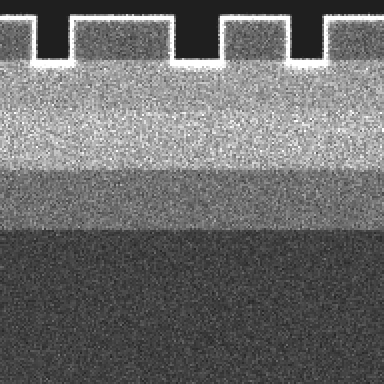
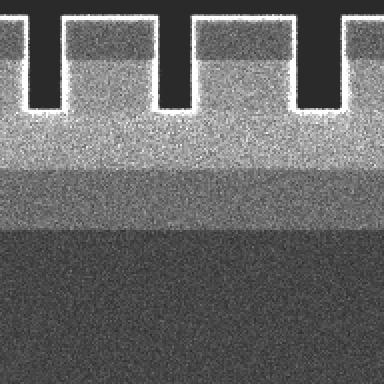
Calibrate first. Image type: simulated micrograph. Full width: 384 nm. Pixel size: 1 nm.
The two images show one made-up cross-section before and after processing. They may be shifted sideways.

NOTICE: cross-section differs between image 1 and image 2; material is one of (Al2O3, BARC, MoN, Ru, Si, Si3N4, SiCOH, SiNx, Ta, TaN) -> removed: Al2O3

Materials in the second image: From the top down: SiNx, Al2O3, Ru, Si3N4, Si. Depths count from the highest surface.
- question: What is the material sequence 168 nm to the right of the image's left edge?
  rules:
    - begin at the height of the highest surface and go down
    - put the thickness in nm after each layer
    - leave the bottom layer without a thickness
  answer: empty 94, Ru 60, Si3N4 60, Si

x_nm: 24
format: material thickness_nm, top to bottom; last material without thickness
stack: SiNx 44, Al2O3 50, Ru 60, Si3N4 60, Si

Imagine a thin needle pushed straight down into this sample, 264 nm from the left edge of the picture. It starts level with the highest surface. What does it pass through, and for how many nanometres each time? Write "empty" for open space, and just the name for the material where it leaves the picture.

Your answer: SiNx 44, Al2O3 50, Ru 60, Si3N4 60, Si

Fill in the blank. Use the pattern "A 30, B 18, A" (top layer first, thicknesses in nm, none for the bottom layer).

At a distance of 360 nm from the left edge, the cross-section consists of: SiNx 44, Al2O3 50, Ru 60, Si3N4 60, Si